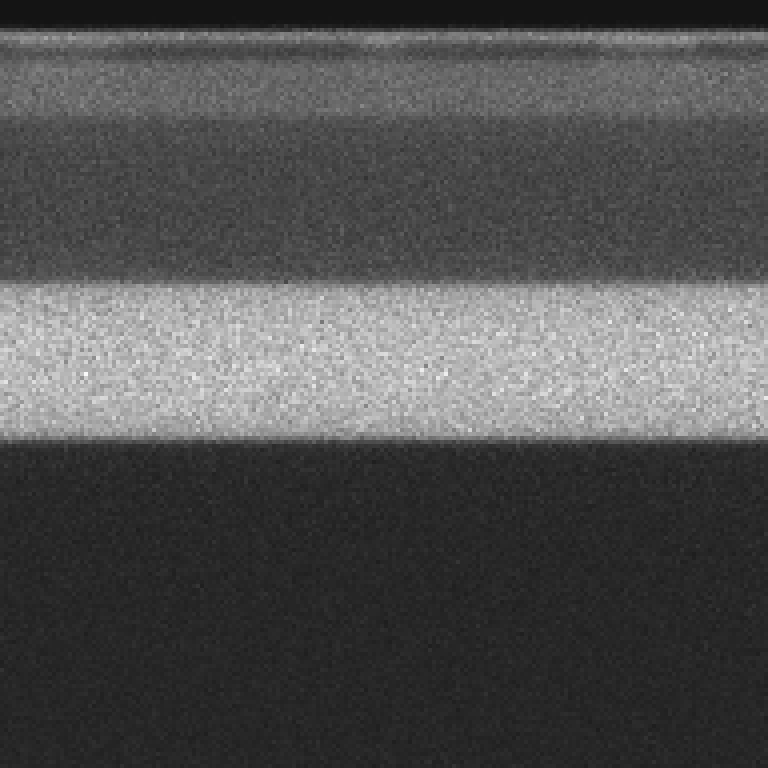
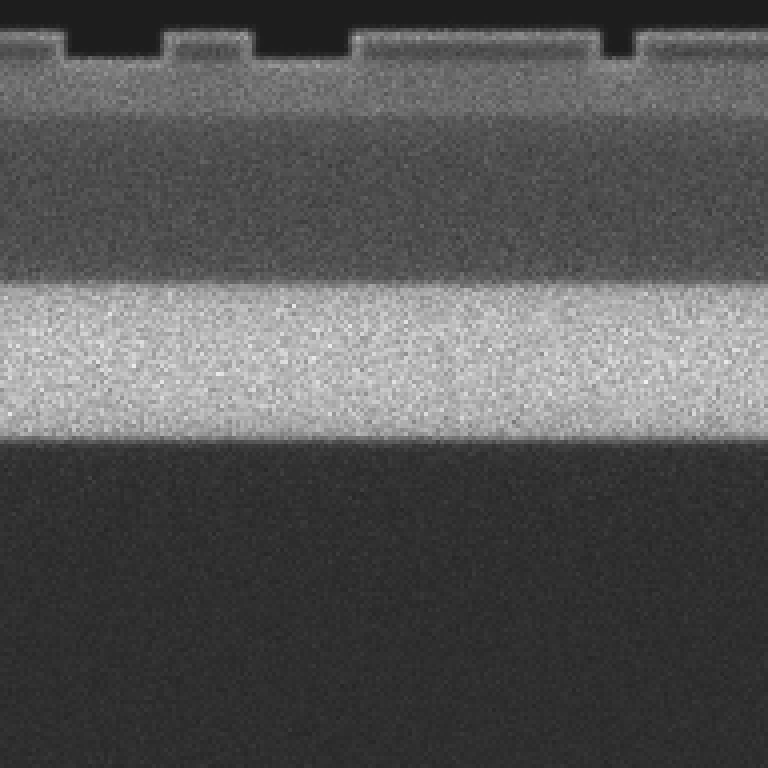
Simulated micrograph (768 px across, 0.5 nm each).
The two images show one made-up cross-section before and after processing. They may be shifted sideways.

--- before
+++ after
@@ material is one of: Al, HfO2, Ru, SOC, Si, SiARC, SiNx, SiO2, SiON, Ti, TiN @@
SOC removed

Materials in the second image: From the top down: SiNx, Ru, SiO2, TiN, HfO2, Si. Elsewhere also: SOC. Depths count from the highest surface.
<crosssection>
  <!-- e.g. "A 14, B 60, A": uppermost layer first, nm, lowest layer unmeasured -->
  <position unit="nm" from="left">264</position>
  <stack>SiNx 14, Ru 28, SiO2 14, TiN 70, HfO2 78, Si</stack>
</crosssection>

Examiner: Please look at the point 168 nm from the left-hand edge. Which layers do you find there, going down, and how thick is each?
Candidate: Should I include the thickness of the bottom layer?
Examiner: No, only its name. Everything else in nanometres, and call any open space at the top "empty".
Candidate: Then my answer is empty 14, Ru 28, SiO2 14, TiN 70, HfO2 78, Si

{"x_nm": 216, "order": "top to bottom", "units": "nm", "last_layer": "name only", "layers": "SiNx 14, Ru 28, SiO2 14, TiN 70, HfO2 78, Si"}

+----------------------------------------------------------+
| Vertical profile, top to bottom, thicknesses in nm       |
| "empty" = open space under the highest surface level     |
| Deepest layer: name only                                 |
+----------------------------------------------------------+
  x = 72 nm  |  empty 14, Ru 28, SiO2 14, TiN 70, HfO2 78, Si